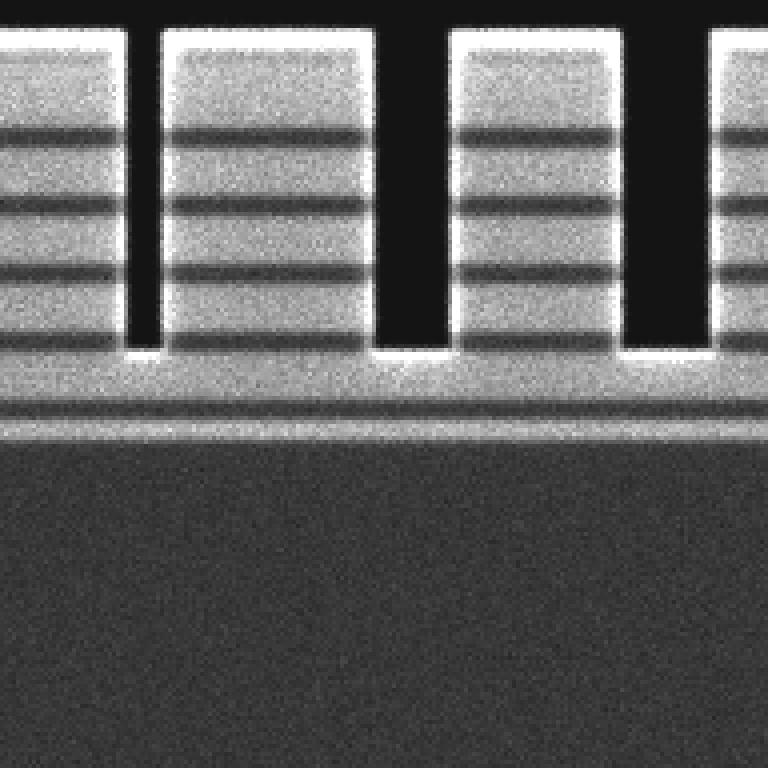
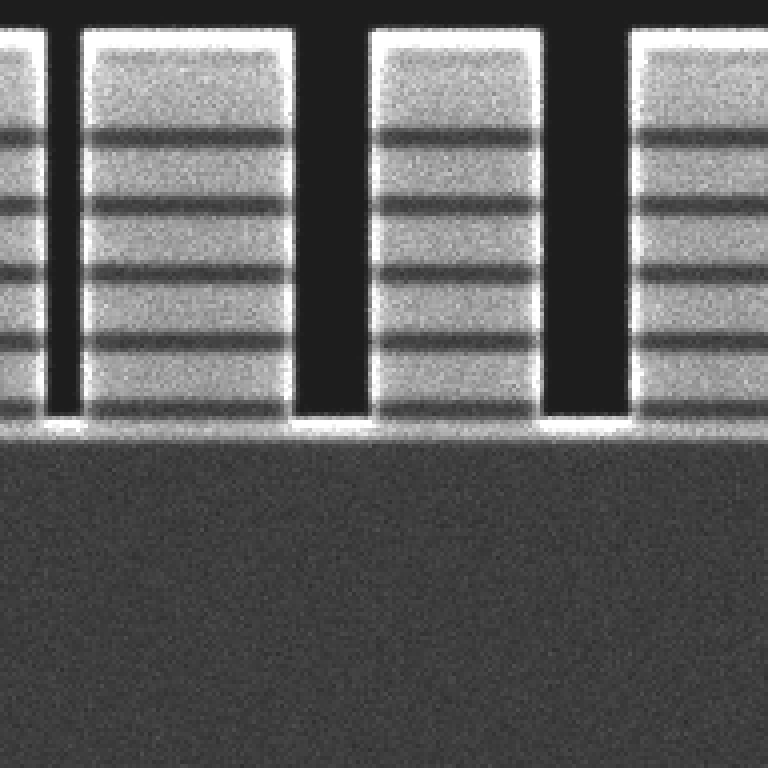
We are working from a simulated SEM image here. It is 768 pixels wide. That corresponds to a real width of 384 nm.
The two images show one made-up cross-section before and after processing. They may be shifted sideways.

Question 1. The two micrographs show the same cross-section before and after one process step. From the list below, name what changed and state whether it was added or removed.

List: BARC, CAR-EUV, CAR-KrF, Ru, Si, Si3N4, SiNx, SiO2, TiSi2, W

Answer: Ru and Si, removed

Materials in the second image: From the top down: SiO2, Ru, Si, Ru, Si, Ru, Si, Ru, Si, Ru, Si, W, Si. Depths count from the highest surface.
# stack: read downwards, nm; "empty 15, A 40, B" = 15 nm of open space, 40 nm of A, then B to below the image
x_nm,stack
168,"empty 194, W 10, Si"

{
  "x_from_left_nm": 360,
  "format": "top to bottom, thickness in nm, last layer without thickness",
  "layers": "SiO2 16, Ru 32, Si 10, Ru 24, Si 10, Ru 24, Si 10, Ru 24, Si 10, Ru 24, Si 10, W 10, Si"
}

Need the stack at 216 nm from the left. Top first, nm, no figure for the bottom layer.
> SiO2 16, Ru 32, Si 10, Ru 24, Si 10, Ru 24, Si 10, Ru 24, Si 10, Ru 24, Si 10, W 10, Si